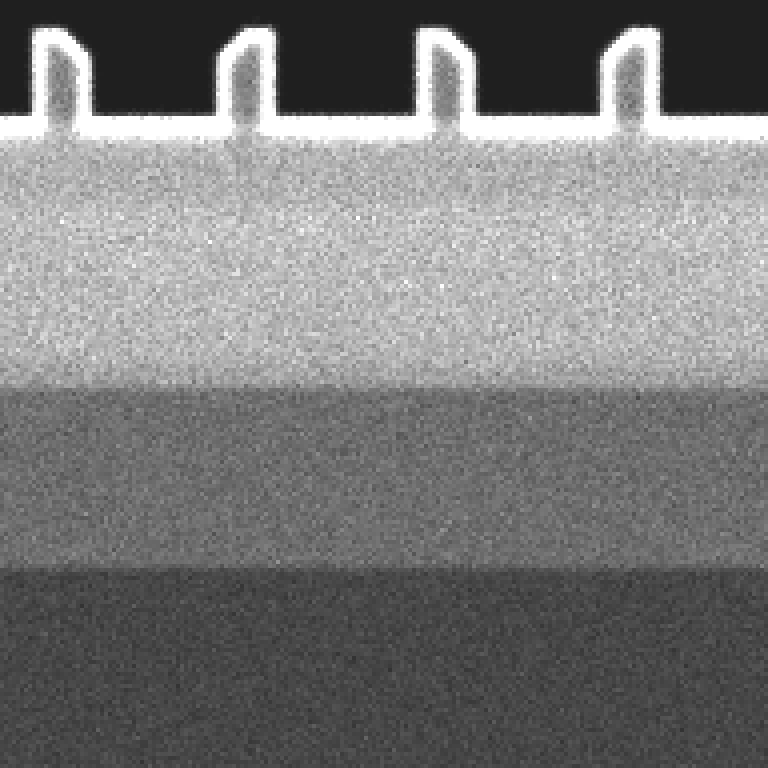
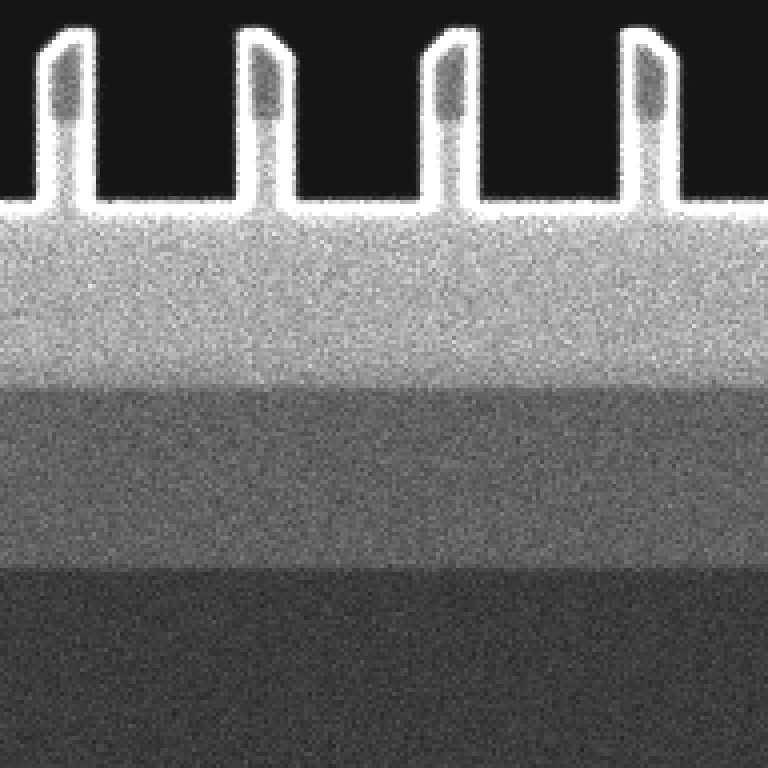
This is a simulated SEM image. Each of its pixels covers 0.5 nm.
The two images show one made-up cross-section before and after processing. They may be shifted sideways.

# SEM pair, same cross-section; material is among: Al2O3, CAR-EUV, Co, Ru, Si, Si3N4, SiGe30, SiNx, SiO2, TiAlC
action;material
removed;Al2O3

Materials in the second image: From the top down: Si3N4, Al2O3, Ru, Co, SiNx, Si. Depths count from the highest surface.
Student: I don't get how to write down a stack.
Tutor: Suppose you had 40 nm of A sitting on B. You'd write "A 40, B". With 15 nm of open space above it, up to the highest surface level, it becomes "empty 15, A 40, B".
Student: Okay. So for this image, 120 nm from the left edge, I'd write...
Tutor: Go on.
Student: Si3N4 44, Al2O3 42, Ru 80, Co 12, SiNx 90, Si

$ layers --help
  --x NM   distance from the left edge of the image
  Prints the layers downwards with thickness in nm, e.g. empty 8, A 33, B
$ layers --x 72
empty 86, Ru 80, Co 12, SiNx 90, Si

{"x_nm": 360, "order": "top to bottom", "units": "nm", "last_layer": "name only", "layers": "empty 86, Ru 80, Co 12, SiNx 90, Si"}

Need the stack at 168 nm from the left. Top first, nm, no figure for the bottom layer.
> empty 86, Ru 80, Co 12, SiNx 90, Si